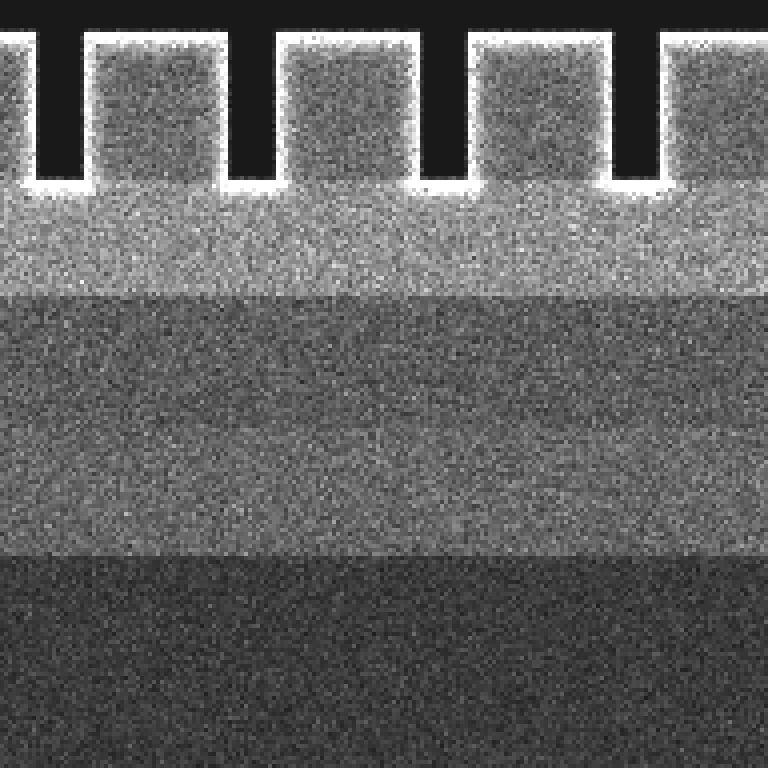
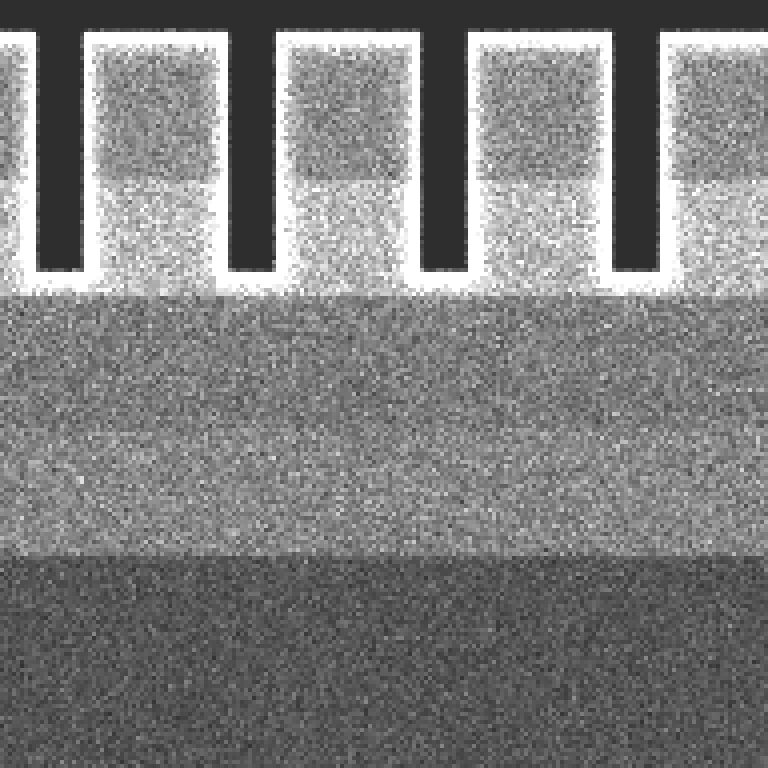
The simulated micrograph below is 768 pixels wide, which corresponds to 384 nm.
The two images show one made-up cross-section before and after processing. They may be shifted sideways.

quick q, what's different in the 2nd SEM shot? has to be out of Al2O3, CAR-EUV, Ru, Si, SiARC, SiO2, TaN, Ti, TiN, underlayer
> SiO2 removed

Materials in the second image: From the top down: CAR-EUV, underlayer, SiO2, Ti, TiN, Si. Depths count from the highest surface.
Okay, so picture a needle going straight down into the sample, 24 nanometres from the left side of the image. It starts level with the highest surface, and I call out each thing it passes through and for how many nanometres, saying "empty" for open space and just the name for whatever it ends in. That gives empty 120, SiO2 12, Ti 66, TiN 64, Si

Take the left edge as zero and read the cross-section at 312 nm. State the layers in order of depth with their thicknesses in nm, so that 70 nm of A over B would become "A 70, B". empty 120, SiO2 12, Ti 66, TiN 64, Si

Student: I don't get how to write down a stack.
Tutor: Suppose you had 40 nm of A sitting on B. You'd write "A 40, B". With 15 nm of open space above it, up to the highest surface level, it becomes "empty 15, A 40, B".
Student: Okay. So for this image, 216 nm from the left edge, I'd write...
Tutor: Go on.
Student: empty 120, SiO2 12, Ti 66, TiN 64, Si